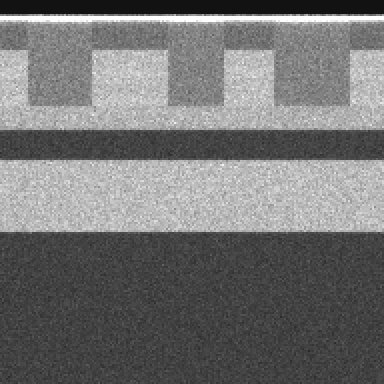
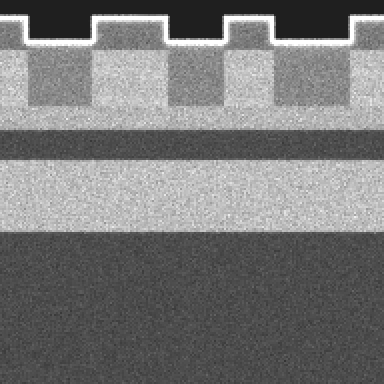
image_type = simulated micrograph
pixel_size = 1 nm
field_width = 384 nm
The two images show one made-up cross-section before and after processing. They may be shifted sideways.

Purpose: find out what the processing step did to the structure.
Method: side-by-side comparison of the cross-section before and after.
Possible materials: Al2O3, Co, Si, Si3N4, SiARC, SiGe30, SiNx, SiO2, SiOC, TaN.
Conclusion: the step removed Si3N4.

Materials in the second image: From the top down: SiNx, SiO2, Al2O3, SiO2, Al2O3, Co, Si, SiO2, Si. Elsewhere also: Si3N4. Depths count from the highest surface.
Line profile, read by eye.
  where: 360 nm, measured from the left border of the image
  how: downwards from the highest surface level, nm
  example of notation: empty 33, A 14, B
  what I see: SiNx 34, SiO2 18, Al2O3 10, SiO2 18, Al2O3 10, Co 24, Si 30, SiO2 72, Si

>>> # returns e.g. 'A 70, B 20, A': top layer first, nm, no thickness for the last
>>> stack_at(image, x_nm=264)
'SiNx 34, SiO2 18, Al2O3 10, SiO2 18, Al2O3 10, Co 24, Si 30, SiO2 72, Si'